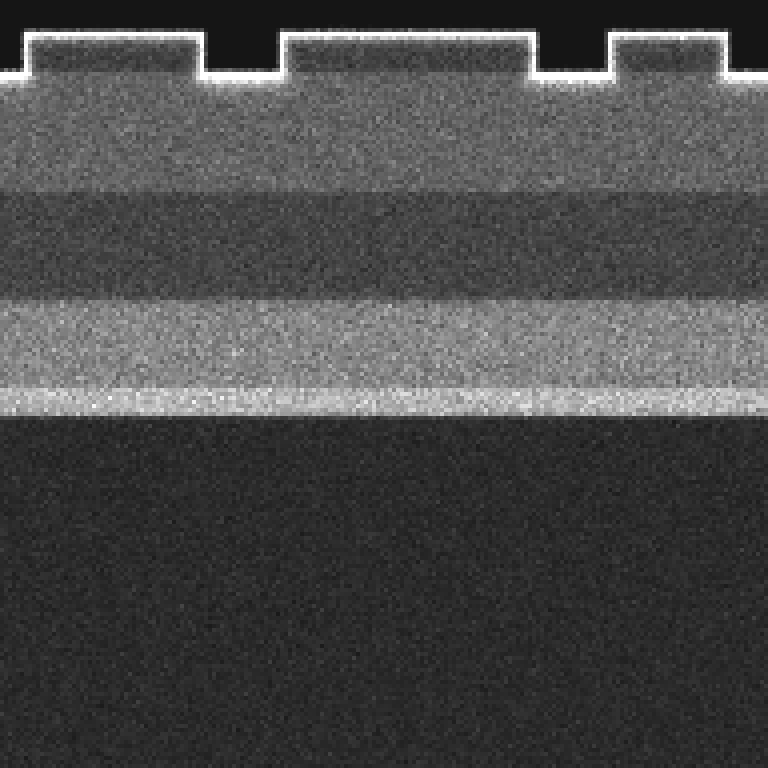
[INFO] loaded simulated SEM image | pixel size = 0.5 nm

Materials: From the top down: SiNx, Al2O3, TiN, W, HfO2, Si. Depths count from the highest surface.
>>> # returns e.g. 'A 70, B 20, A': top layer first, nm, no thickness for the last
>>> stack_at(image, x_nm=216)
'SiNx 20, Al2O3 60, TiN 54, W 44, HfO2 14, Si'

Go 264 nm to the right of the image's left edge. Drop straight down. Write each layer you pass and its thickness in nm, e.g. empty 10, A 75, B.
SiNx 20, Al2O3 60, TiN 54, W 44, HfO2 14, Si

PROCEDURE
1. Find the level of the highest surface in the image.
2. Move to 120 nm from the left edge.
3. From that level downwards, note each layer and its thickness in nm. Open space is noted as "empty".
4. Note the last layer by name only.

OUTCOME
empty 20, Al2O3 60, TiN 54, W 44, HfO2 14, Si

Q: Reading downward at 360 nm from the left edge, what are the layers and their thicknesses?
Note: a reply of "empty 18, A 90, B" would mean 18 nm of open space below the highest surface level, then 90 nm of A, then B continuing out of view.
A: SiNx 20, Al2O3 60, TiN 54, W 44, HfO2 14, Si